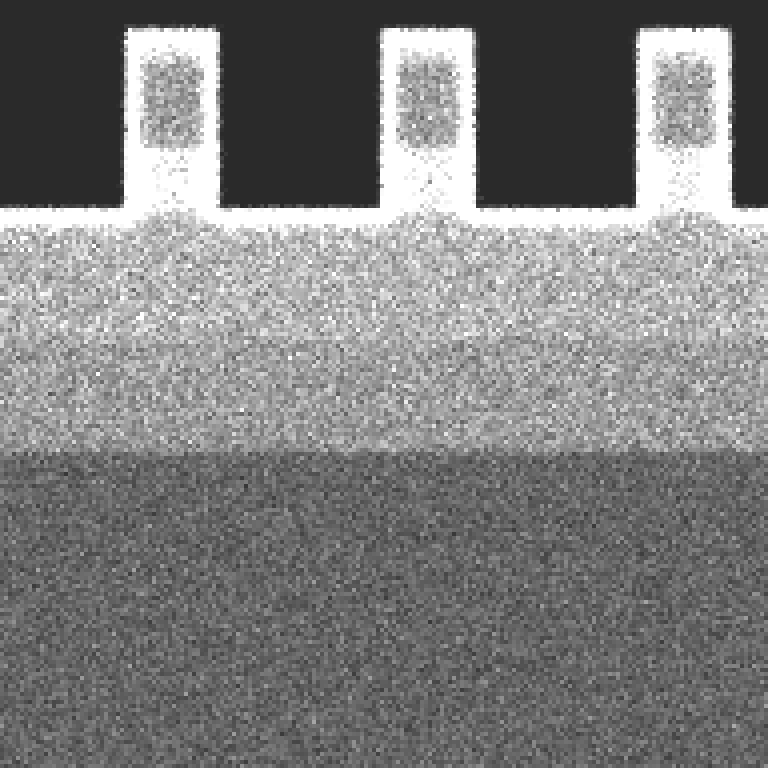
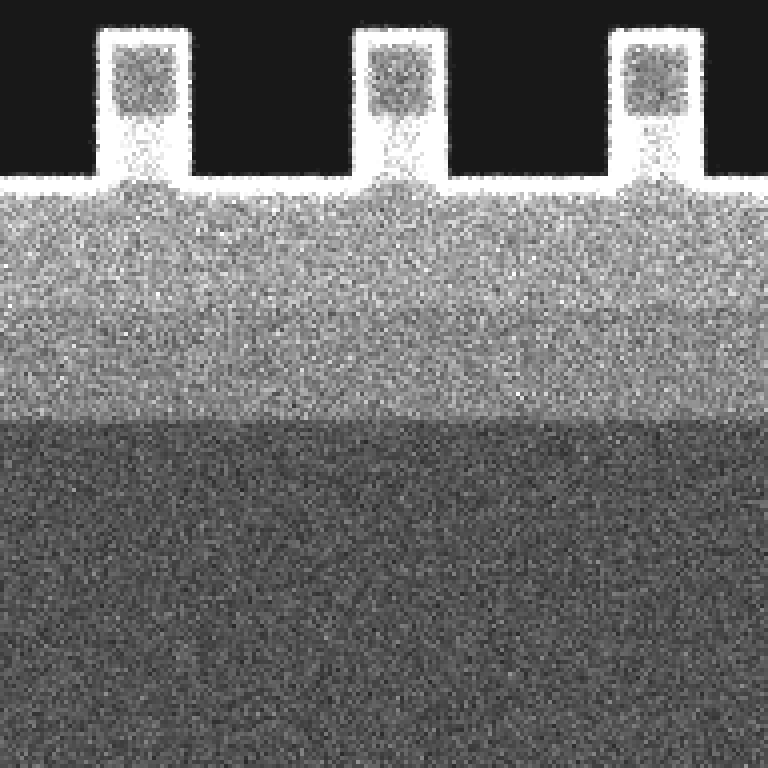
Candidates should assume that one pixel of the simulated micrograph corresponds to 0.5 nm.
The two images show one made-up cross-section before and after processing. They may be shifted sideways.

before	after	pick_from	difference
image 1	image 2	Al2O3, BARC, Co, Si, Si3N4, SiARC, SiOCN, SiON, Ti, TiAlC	SiARC removed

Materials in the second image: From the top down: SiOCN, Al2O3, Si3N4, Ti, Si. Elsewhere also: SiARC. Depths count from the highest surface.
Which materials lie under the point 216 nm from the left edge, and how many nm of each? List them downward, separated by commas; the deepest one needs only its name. SiOCN 42, Al2O3 32, Si3N4 64, Ti 56, Si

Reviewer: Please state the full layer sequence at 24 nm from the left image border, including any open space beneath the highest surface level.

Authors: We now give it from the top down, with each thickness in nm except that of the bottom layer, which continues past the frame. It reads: empty 74, Si3N4 64, Ti 56, Si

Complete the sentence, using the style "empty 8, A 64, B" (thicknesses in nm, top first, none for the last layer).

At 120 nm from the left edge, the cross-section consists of empty 74, Si3N4 64, Ti 56, Si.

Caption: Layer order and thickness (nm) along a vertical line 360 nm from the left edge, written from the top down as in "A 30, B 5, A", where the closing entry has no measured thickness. empty 74, Si3N4 64, Ti 56, Si